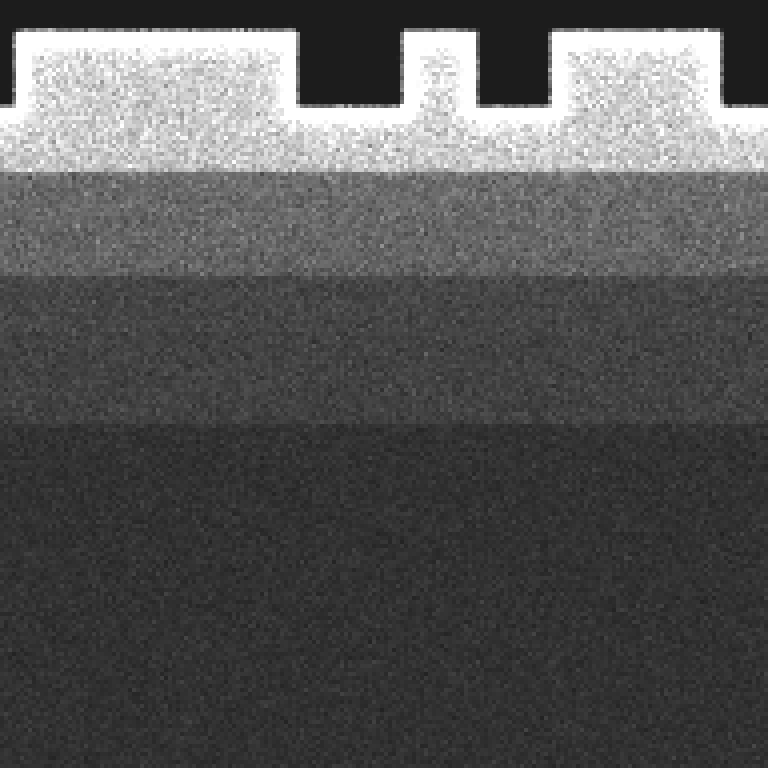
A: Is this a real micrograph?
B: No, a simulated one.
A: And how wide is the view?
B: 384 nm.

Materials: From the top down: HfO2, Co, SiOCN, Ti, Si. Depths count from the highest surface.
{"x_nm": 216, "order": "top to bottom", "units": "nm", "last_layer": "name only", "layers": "HfO2 70, Co 52, SiOCN 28, Ti 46, Si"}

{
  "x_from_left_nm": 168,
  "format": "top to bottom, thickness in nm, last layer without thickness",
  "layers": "empty 38, HfO2 32, Co 52, SiOCN 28, Ti 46, Si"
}